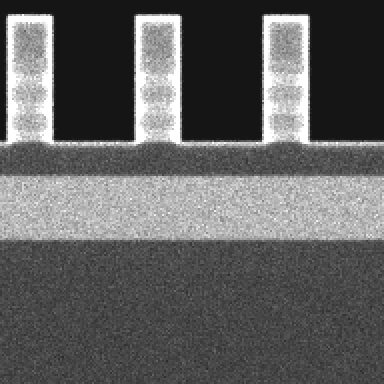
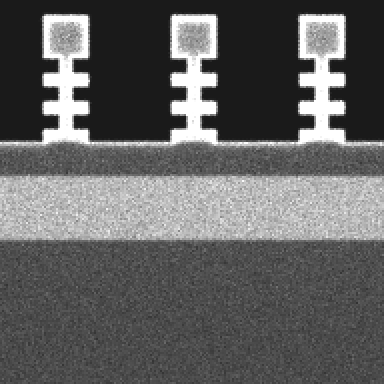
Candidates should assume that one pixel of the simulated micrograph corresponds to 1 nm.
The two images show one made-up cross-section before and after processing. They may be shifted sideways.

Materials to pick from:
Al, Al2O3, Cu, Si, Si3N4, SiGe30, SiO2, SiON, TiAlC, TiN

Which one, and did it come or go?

TiN - removed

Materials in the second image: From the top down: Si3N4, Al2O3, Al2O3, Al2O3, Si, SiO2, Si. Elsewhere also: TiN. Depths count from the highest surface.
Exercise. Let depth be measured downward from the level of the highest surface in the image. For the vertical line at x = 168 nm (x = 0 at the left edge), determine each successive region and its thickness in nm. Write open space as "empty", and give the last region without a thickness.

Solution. empty 126, Si 34, SiO2 64, Si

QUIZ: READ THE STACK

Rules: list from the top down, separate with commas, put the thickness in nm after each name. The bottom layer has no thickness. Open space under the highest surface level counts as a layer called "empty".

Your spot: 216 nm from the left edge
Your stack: empty 126, Si 34, SiO2 64, Si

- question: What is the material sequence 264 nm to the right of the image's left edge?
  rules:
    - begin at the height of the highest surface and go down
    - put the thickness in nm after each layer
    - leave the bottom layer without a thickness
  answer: empty 126, Si 34, SiO2 64, Si